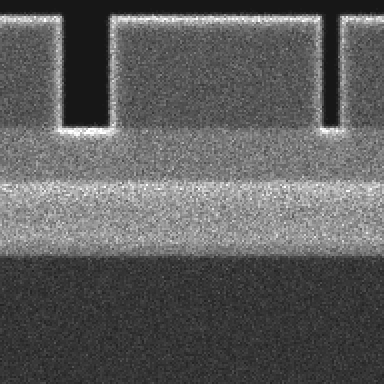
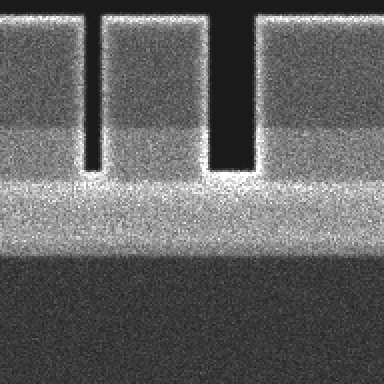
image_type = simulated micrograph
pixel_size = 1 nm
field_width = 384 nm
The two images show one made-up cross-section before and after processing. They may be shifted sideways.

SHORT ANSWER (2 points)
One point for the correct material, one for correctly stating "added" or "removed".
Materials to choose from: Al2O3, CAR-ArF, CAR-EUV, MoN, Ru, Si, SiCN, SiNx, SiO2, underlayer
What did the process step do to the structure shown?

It removed SiO2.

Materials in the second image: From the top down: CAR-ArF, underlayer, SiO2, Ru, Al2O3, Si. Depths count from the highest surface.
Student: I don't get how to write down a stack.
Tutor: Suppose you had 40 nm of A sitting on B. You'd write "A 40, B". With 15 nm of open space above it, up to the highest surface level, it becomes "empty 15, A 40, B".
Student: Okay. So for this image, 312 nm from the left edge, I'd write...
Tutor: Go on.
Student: CAR-ArF 66, underlayer 46, SiO2 54, Ru 62, Al2O3 12, Si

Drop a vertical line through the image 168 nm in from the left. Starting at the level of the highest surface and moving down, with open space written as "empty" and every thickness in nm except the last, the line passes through CAR-ArF 66, underlayer 46, SiO2 54, Ru 62, Al2O3 12, Si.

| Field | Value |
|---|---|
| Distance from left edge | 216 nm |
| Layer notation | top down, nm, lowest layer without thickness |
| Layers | empty 156, SiO2 10, Ru 62, Al2O3 12, Si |